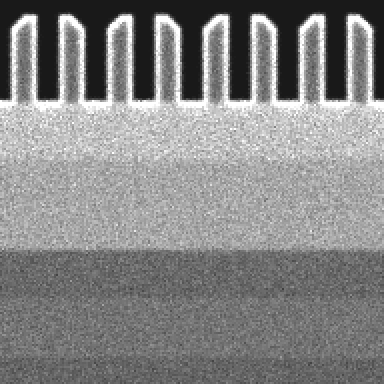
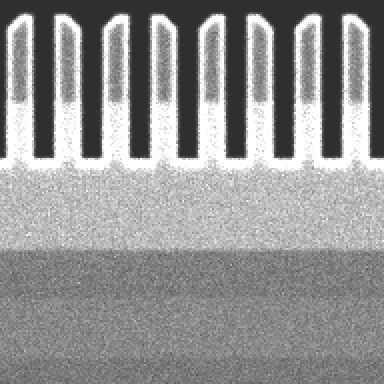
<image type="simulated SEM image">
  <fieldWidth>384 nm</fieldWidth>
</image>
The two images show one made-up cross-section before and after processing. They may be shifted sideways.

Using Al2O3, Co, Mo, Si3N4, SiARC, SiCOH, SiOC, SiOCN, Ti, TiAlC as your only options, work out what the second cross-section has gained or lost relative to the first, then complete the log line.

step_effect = removed Co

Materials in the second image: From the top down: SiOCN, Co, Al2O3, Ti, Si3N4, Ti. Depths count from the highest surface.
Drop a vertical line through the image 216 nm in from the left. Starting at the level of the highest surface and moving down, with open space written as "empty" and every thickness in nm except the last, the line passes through SiOCN 86, Co 58, Al2O3 90, Ti 48, Si3N4 60, Ti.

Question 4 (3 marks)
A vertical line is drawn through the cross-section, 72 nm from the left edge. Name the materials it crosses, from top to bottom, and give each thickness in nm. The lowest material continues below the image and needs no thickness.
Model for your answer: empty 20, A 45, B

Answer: empty 6, SiOCN 80, Co 58, Al2O3 90, Ti 48, Si3N4 60, Ti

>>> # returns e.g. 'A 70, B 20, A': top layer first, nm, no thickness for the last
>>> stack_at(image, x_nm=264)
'empty 6, SiOCN 80, Co 58, Al2O3 90, Ti 48, Si3N4 60, Ti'